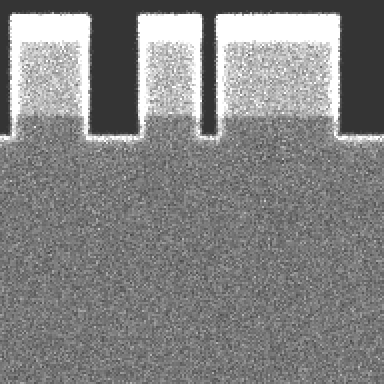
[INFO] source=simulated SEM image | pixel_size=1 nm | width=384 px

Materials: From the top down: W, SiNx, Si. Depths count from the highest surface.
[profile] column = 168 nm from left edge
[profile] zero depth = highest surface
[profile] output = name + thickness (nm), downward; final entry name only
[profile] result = W 24, SiNx 76, Si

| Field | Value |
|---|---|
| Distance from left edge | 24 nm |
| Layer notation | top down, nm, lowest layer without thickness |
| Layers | W 24, SiNx 76, Si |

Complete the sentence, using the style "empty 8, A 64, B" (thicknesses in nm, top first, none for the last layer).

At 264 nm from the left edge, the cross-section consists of W 24, SiNx 76, Si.